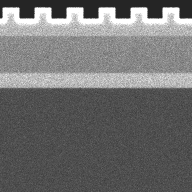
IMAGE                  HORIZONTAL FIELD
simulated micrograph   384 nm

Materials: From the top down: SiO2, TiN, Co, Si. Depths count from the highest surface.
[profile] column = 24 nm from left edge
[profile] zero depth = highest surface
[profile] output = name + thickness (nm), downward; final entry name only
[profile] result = SiO2 56, TiN 74, Co 30, Si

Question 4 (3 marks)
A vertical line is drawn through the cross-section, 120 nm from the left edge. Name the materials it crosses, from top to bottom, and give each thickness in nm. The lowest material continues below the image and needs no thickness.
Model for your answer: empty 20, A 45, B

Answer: empty 22, SiO2 34, TiN 74, Co 30, Si